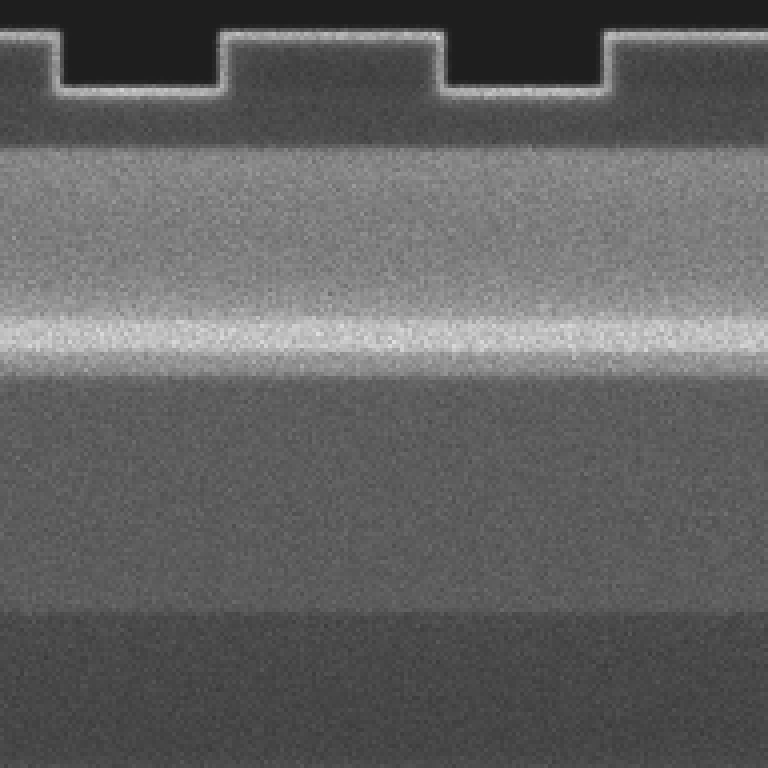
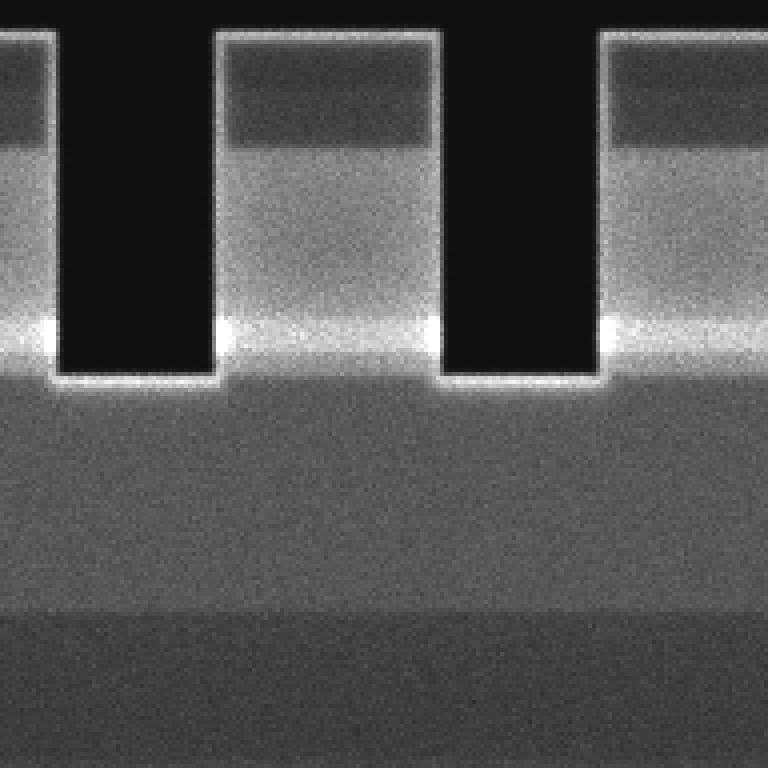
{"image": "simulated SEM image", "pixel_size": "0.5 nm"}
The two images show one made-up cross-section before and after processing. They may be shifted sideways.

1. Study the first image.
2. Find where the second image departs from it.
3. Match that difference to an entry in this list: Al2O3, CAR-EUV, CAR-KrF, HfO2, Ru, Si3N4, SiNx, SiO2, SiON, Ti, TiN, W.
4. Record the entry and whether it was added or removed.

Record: HfO2 and Ru and Si3N4 and W / removed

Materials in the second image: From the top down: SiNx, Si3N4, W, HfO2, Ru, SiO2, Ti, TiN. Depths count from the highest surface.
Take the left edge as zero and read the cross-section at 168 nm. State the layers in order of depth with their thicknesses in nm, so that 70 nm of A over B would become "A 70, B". SiNx 28, Si3N4 30, W 86, HfO2 16, Ru 12, SiO2 118, Ti 74, TiN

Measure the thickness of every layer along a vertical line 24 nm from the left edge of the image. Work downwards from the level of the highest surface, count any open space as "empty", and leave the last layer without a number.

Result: SiNx 28, Si3N4 30, W 86, HfO2 16, Ru 12, SiO2 118, Ti 74, TiN